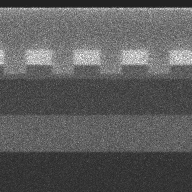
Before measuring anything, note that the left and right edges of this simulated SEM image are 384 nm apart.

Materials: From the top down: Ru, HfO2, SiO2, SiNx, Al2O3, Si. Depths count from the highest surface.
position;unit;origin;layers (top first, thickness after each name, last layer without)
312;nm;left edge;Ru 132, SiO2 10, SiNx 72, Al2O3 74, Si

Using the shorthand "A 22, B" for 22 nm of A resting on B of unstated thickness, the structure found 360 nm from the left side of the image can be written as Ru 84, HfO2 30, SiO2 28, SiNx 72, Al2O3 74, Si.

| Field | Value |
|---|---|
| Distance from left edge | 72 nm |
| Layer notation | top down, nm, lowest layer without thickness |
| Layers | Ru 84, HfO2 30, SiO2 28, SiNx 72, Al2O3 74, Si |